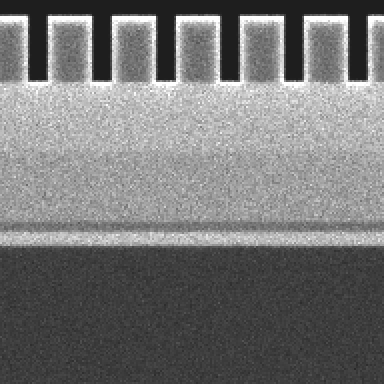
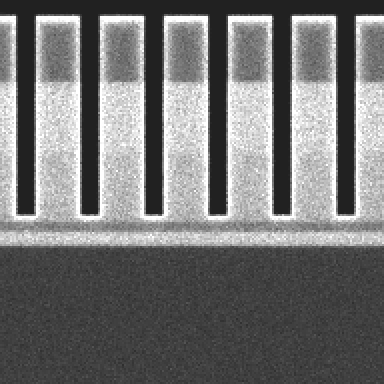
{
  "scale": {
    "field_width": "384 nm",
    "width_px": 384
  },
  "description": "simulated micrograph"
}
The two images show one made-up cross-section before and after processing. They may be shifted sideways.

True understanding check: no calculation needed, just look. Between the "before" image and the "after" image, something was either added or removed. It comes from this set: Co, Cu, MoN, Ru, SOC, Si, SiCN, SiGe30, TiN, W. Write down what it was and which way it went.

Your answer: Co and Ru (removed)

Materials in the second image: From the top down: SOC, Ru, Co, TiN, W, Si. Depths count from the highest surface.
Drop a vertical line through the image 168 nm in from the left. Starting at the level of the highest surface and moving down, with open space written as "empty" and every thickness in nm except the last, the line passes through SOC 66, Ru 70, Co 70, TiN 10, W 14, Si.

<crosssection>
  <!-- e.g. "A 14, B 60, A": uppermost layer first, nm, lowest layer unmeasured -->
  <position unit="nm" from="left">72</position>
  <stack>SOC 66, Ru 70, Co 70, TiN 10, W 14, Si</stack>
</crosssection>